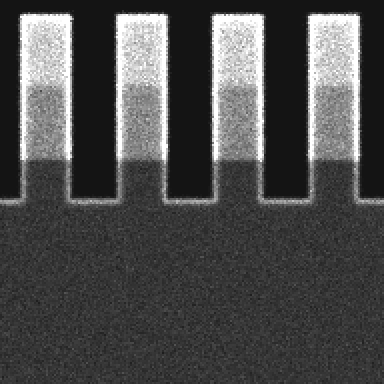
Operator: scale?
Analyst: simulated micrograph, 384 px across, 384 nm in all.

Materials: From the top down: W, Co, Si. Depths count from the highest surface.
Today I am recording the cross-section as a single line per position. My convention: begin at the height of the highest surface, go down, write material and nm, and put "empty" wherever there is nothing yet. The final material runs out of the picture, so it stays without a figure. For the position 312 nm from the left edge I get W 70, Co 74, Si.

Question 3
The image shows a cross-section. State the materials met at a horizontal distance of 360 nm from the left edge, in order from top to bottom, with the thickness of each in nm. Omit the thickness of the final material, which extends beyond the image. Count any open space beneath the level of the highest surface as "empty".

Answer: empty 184, Si